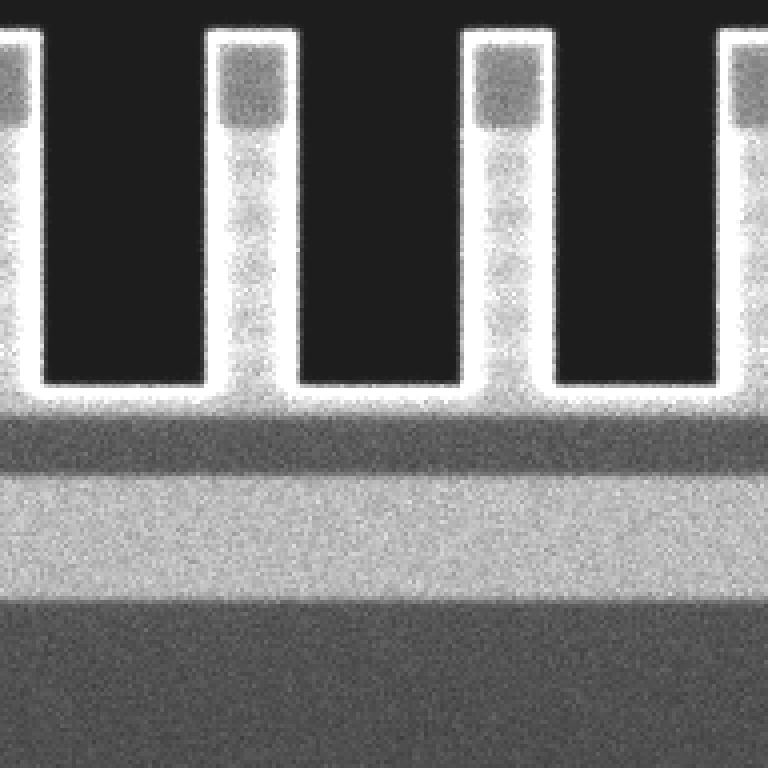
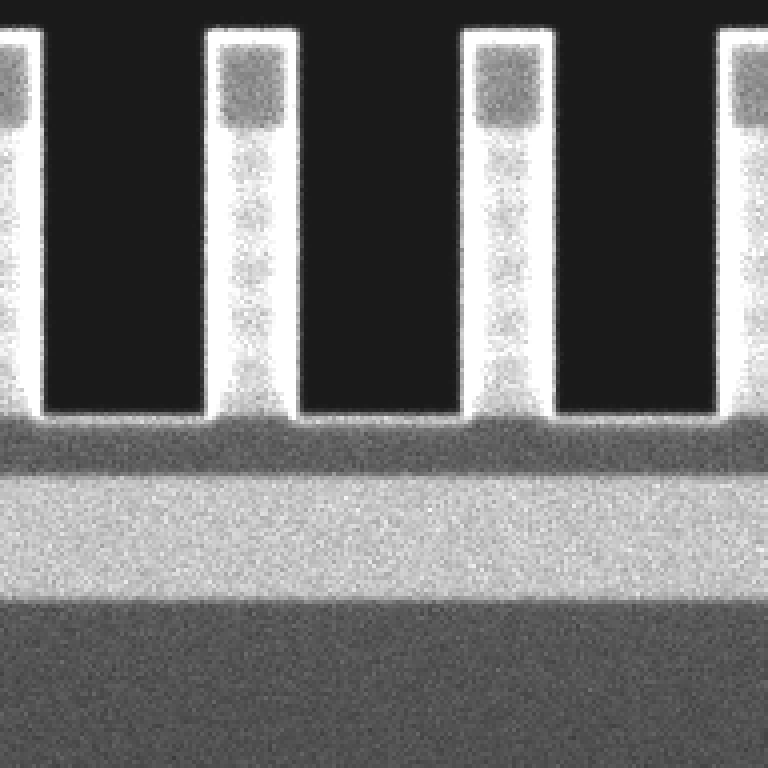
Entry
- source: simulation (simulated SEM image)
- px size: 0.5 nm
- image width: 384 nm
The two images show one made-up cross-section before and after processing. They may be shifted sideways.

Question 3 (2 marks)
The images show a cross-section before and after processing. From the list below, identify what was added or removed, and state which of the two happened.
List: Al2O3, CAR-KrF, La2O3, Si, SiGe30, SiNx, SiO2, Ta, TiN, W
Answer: TiN was removed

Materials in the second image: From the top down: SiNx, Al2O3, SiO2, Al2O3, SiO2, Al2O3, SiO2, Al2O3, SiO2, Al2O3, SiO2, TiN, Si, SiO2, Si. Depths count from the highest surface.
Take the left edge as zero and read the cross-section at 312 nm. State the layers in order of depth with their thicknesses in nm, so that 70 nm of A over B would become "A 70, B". empty 192, Si 30, SiO2 62, Si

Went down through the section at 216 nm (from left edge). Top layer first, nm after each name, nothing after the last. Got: empty 192, Si 30, SiO2 62, Si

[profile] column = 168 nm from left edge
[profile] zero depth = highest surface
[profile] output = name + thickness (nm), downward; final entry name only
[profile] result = empty 192, Si 30, SiO2 62, Si